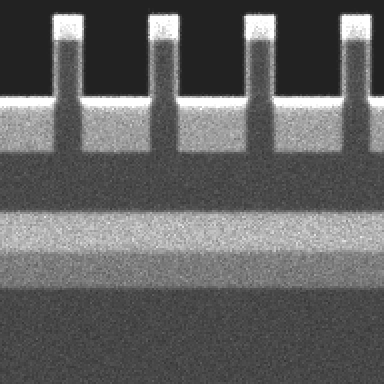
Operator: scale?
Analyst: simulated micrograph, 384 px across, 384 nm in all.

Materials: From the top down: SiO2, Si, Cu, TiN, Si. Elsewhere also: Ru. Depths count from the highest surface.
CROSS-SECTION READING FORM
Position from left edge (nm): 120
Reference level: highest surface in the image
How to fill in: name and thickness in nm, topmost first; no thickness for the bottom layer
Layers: empty 82, SiO2 54, Si 60, Cu 40, TiN 36, Si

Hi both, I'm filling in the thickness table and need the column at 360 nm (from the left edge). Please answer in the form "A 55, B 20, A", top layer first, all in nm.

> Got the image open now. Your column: Ru 24, Si 172, Cu 40, TiN 36, Si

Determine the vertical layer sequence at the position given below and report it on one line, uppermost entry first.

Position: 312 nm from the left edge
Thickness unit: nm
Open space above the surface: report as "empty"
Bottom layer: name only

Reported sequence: empty 82, SiO2 54, Si 60, Cu 40, TiN 36, Si